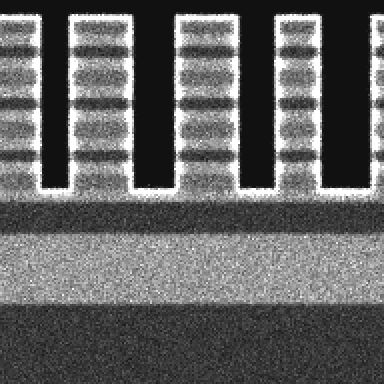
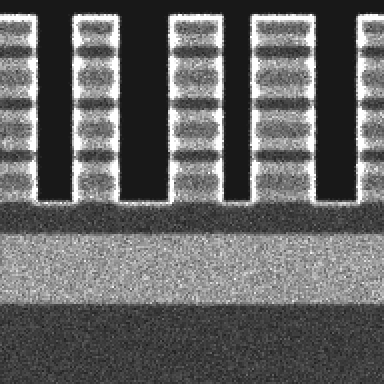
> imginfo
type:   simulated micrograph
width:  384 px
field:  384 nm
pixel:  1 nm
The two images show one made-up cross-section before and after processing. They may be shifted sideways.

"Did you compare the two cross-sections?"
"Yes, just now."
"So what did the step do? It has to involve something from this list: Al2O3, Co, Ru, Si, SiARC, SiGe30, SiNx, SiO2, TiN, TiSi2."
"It removed Co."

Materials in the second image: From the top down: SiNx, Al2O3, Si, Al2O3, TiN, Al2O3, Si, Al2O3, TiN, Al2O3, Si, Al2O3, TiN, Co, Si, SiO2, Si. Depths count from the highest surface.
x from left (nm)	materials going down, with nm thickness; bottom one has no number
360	SiNx 18, Al2O3 12, Si 12, Al2O3 12, TiN 16, Al2O3 12, Si 12, Al2O3 12, TiN 16, Al2O3 12, Si 12, Al2O3 12, TiN 16, Co 12, Si 32, SiO2 70, Si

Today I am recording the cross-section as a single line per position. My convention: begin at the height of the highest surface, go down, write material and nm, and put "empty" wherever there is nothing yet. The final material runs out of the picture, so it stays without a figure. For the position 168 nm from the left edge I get empty 186, Si 32, SiO2 70, Si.